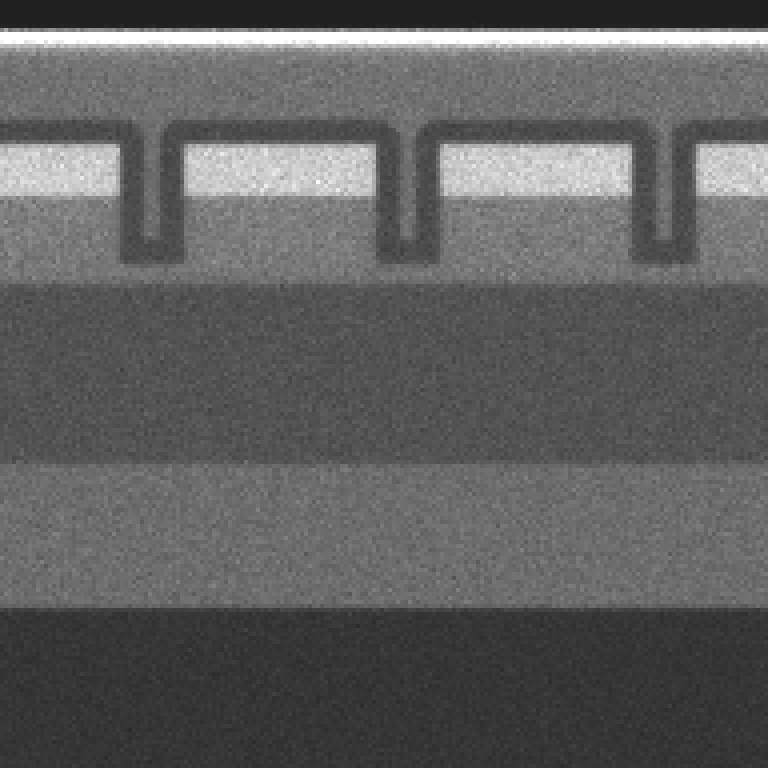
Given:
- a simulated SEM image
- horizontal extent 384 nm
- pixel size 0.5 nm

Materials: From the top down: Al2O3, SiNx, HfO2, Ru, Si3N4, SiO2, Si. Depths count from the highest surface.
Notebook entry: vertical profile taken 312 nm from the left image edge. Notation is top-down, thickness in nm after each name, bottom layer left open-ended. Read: Al2O3 44, SiNx 12, HfO2 26, Ru 44, Si3N4 90, SiO2 72, Si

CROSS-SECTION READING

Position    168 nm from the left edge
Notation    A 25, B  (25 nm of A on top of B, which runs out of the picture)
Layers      Al2O3 44, SiNx 12, HfO2 26, Ru 44, Si3N4 90, SiO2 72, Si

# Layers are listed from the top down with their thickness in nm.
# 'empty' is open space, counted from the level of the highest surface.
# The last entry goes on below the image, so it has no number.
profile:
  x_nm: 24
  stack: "Al2O3 44, SiNx 12, HfO2 26, Ru 44, Si3N4 90, SiO2 72, Si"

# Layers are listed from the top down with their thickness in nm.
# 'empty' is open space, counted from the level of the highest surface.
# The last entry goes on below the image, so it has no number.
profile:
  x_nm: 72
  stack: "Al2O3 104, SiNx 12, Ru 10, Si3N4 90, SiO2 72, Si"